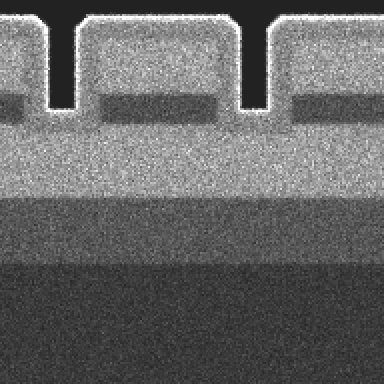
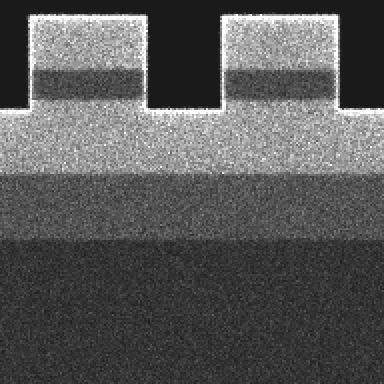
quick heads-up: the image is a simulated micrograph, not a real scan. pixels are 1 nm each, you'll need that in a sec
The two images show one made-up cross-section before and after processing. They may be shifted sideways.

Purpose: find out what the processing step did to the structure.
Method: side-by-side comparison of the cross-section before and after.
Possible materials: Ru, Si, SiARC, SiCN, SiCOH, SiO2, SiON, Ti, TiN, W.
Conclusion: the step removed Ru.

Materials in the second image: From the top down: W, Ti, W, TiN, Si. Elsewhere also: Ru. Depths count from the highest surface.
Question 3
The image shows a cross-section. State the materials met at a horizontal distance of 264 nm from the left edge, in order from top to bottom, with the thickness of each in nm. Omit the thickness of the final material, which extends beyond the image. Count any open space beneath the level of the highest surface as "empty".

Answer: W 54, Ti 30, W 74, TiN 66, Si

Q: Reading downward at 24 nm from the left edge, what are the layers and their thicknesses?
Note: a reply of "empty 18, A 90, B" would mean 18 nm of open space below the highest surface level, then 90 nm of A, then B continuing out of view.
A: empty 94, W 64, TiN 66, Si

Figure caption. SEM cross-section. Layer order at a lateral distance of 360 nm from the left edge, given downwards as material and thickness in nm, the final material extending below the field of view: empty 94, W 64, TiN 66, Si